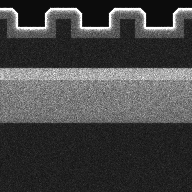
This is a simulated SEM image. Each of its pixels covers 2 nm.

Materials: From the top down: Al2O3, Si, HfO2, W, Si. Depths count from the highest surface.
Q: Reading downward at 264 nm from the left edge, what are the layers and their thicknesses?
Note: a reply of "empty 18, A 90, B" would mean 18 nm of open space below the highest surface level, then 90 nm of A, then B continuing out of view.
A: Al2O3 22, Si 98, HfO2 24, W 86, Si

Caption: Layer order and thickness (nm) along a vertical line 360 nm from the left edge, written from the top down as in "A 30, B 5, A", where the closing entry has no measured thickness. Al2O3 60, Si 60, HfO2 24, W 86, Si